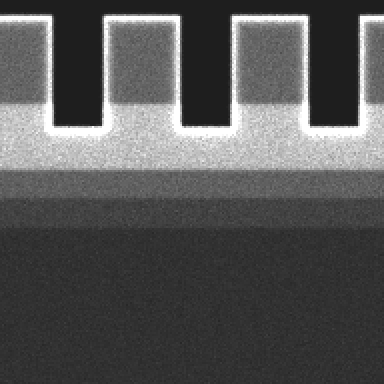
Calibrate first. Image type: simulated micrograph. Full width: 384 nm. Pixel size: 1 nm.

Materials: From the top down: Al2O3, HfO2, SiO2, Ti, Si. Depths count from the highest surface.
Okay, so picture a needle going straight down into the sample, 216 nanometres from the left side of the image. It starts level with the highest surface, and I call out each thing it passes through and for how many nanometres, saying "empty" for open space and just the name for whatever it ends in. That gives empty 112, HfO2 42, SiO2 28, Ti 30, Si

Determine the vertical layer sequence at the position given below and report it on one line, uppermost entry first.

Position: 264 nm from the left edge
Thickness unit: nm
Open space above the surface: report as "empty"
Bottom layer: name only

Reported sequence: Al2O3 88, HfO2 66, SiO2 28, Ti 30, Si